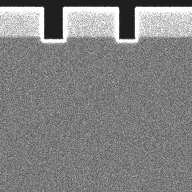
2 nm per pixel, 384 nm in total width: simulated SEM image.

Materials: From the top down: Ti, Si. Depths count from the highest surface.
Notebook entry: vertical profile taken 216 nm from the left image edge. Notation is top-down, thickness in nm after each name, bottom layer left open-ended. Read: Ti 58, Si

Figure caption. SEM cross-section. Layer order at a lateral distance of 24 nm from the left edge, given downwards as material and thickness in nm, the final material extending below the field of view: Ti 58, Si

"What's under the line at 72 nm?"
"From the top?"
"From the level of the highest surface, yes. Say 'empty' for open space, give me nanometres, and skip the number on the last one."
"Ti 58, Si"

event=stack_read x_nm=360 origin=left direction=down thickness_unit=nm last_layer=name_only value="Ti 58, Si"